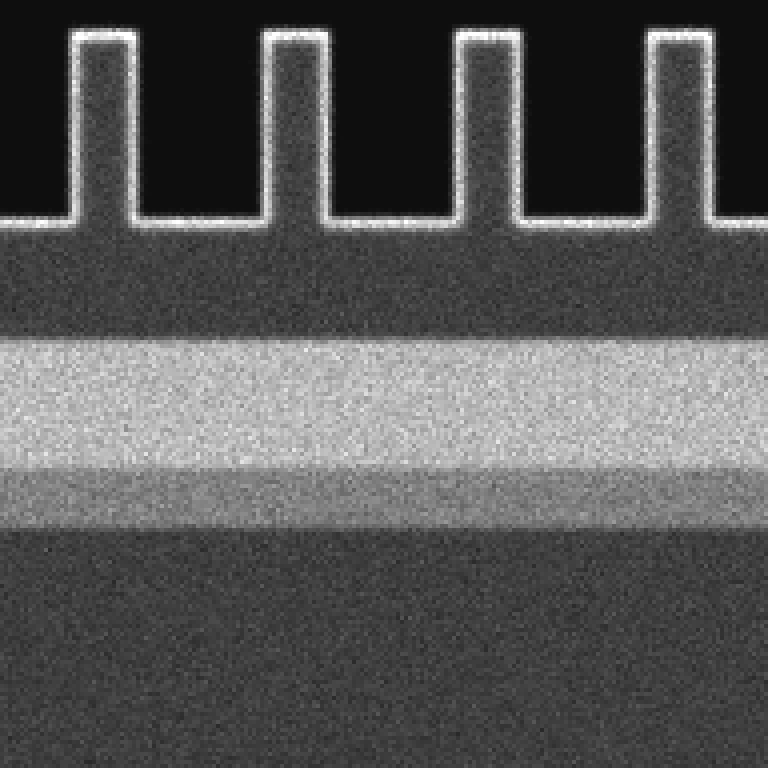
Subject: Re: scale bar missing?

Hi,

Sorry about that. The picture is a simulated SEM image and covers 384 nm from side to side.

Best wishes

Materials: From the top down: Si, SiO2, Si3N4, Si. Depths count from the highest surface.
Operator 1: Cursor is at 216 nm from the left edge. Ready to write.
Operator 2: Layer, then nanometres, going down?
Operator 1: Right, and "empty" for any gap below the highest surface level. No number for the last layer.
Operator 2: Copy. empty 94, Si 60, SiO2 64, Si3N4 30, Si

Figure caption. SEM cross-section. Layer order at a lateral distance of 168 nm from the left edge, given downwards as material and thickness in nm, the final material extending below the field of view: empty 94, Si 60, SiO2 64, Si3N4 30, Si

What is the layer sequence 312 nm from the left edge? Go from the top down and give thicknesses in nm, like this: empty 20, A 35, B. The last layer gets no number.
empty 94, Si 60, SiO2 64, Si3N4 30, Si